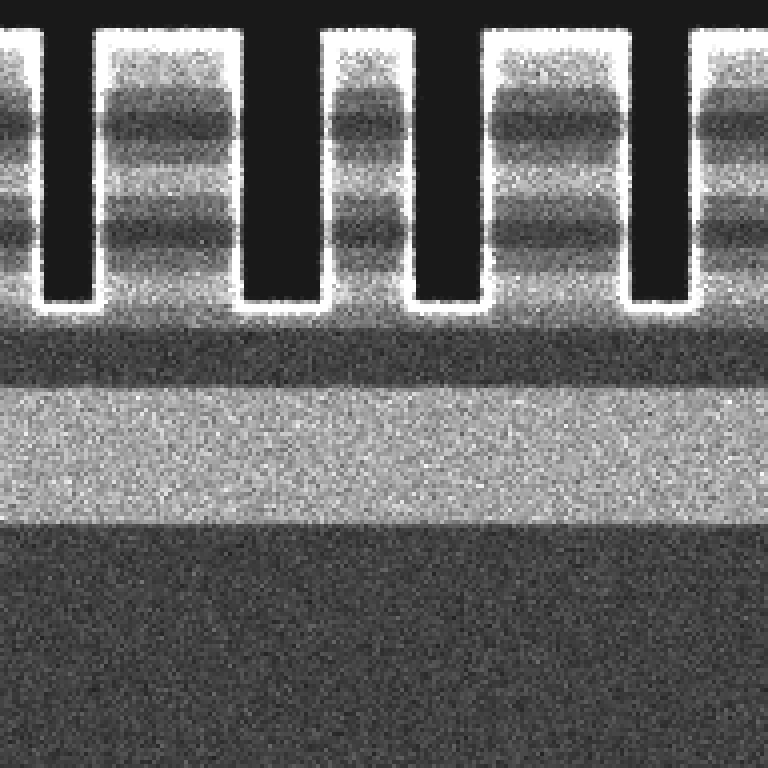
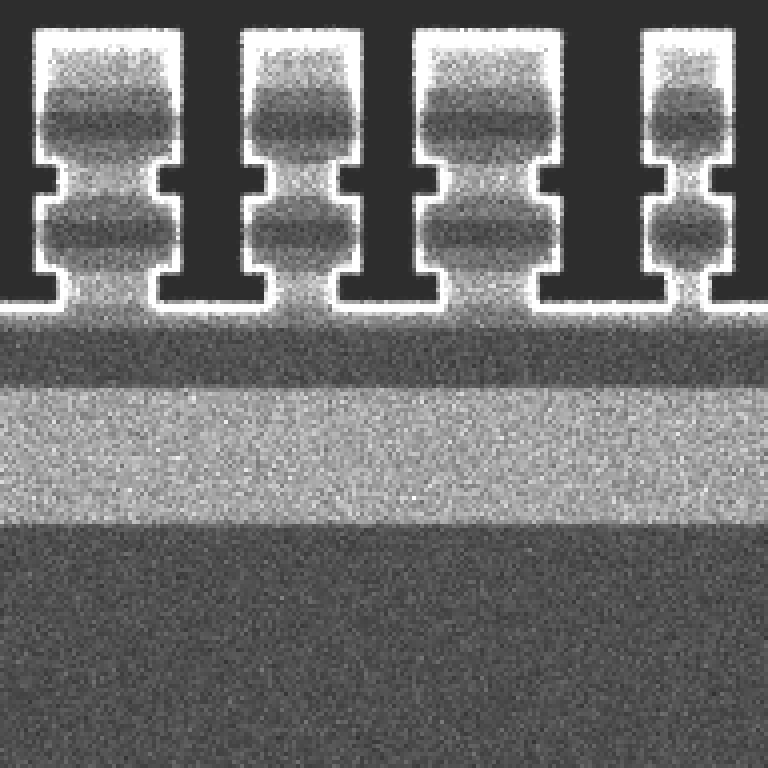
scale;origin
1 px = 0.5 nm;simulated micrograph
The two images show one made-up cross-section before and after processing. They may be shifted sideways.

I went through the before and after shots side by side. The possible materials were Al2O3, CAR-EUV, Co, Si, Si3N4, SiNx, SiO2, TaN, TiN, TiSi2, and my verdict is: removed, Co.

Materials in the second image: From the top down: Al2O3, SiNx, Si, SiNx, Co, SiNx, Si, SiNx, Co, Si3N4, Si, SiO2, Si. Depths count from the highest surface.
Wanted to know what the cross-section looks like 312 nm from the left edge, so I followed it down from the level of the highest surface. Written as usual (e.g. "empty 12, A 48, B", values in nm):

empty 136, Si3N4 12, Si 30, SiO2 68, Si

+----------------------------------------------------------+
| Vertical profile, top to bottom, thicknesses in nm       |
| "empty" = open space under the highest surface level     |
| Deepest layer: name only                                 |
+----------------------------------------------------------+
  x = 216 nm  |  Al2O3 28, SiNx 12, Si 14, SiNx 12, empty 16, SiNx 12, Si 14, SiNx 12, empty 16, Si3N4 12, Si 30, SiO2 68, Si